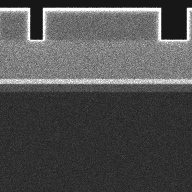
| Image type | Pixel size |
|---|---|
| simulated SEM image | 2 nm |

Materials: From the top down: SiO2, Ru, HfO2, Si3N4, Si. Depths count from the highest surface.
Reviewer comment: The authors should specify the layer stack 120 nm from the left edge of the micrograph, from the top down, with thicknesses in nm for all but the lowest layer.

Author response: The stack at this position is SiO2 64, Ru 78, HfO2 10, Si3N4 16, Si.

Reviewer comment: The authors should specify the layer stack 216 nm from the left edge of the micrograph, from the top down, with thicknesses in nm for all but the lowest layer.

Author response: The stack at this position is SiO2 64, Ru 78, HfO2 10, Si3N4 16, Si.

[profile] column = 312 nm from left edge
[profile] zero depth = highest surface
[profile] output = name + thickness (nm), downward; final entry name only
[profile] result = SiO2 64, Ru 78, HfO2 10, Si3N4 16, Si